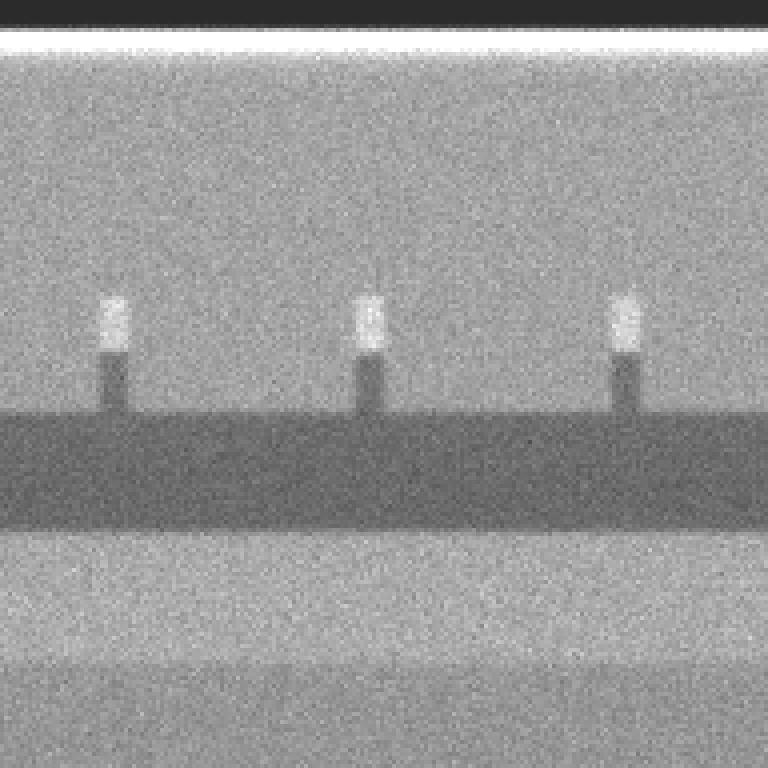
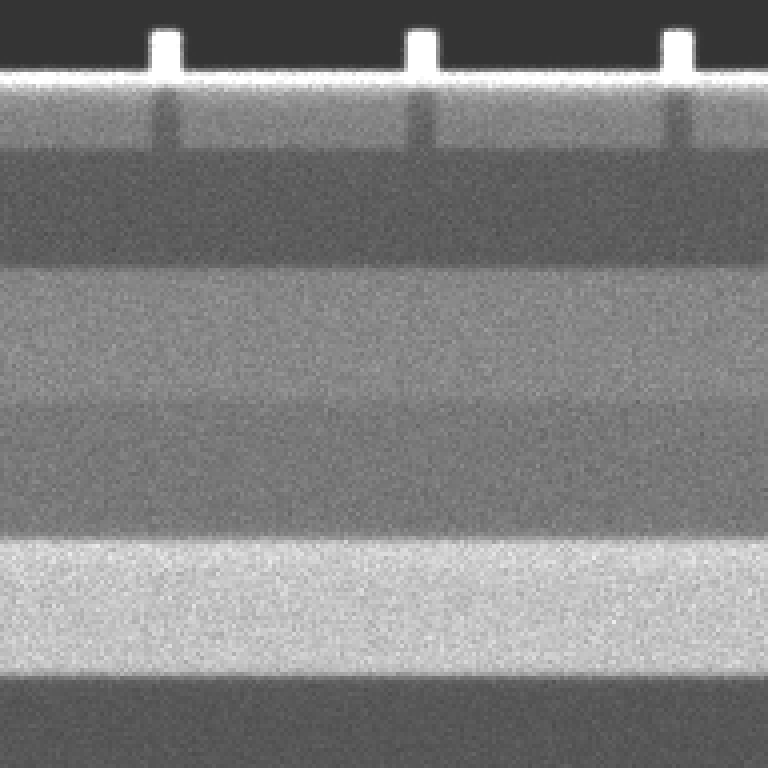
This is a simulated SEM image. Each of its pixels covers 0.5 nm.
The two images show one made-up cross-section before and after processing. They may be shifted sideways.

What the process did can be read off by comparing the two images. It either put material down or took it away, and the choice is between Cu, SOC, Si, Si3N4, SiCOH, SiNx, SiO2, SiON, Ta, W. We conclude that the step removed SOC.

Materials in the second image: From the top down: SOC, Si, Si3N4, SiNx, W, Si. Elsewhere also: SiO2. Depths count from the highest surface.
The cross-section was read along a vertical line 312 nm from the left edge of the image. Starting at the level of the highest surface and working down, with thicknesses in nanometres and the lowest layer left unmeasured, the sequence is empty 20, SOC 38, Si 60, Si3N4 66, SiNx 70, W 68, Si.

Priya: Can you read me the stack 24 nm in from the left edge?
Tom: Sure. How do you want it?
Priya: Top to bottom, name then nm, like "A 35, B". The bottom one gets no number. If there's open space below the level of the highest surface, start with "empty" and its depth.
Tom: empty 20, SOC 38, Si 60, Si3N4 66, SiNx 70, W 68, Si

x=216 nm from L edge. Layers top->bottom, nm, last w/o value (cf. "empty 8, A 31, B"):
SiO2 28, Si 90, Si3N4 66, SiNx 70, W 68, Si